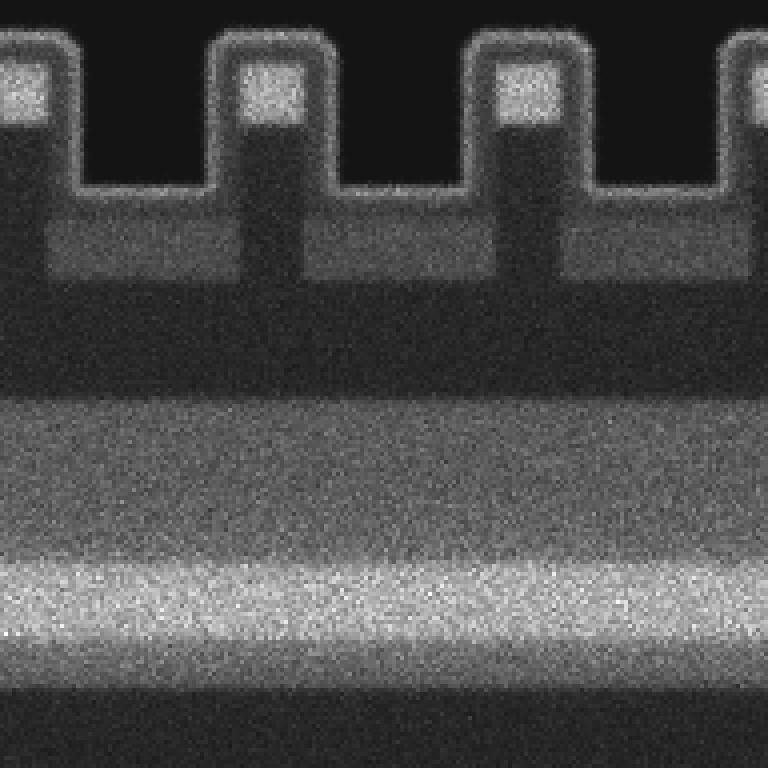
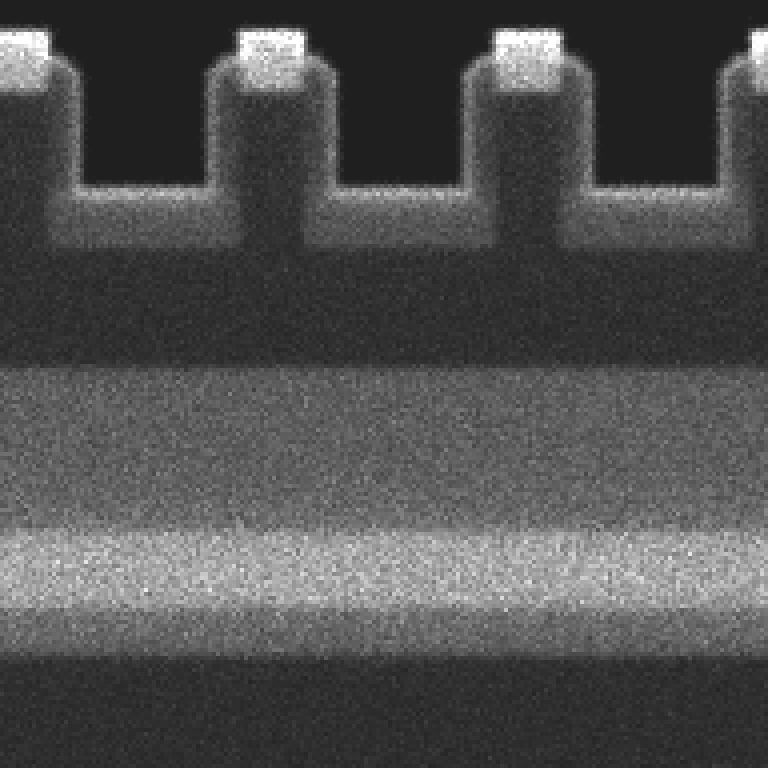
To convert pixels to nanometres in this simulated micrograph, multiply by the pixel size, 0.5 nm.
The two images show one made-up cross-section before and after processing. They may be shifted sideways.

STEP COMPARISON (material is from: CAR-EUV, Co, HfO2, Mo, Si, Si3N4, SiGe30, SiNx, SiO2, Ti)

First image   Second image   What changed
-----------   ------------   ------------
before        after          SiNx, removed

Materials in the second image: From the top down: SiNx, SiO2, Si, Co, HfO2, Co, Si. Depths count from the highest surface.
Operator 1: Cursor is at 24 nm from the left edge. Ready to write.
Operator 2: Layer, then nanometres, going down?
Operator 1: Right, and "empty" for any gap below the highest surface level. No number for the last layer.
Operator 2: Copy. empty 12, SiNx 66, SiO2 30, Si 60, Co 82, HfO2 38, Co 24, Si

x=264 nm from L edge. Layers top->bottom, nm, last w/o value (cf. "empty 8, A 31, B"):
HfO2 30, Si 138, Co 82, HfO2 38, Co 24, Si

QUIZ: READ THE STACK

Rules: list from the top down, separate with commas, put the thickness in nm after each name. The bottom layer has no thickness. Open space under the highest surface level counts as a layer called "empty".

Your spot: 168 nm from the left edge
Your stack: empty 78, SiO2 30, Si 60, Co 82, HfO2 38, Co 24, Si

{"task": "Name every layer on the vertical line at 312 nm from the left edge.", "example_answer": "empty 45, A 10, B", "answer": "empty 78, SiO2 30, Si 60, Co 82, HfO2 38, Co 24, Si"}